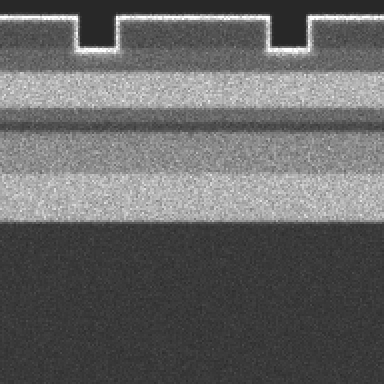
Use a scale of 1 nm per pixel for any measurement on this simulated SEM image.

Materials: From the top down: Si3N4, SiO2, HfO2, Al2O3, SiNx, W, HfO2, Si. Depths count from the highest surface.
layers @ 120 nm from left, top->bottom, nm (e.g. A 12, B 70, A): Si3N4 32, SiO2 24, HfO2 36, Al2O3 14, SiNx 10, W 42, HfO2 48, Si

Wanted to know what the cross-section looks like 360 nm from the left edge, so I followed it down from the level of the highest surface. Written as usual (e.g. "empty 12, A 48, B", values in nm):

Si3N4 32, SiO2 24, HfO2 36, Al2O3 14, SiNx 10, W 42, HfO2 48, Si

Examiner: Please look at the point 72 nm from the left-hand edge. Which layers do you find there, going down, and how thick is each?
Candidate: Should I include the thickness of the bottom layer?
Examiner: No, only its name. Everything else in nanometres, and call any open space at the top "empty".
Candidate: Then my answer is Si3N4 32, SiO2 24, HfO2 36, Al2O3 14, SiNx 10, W 42, HfO2 48, Si